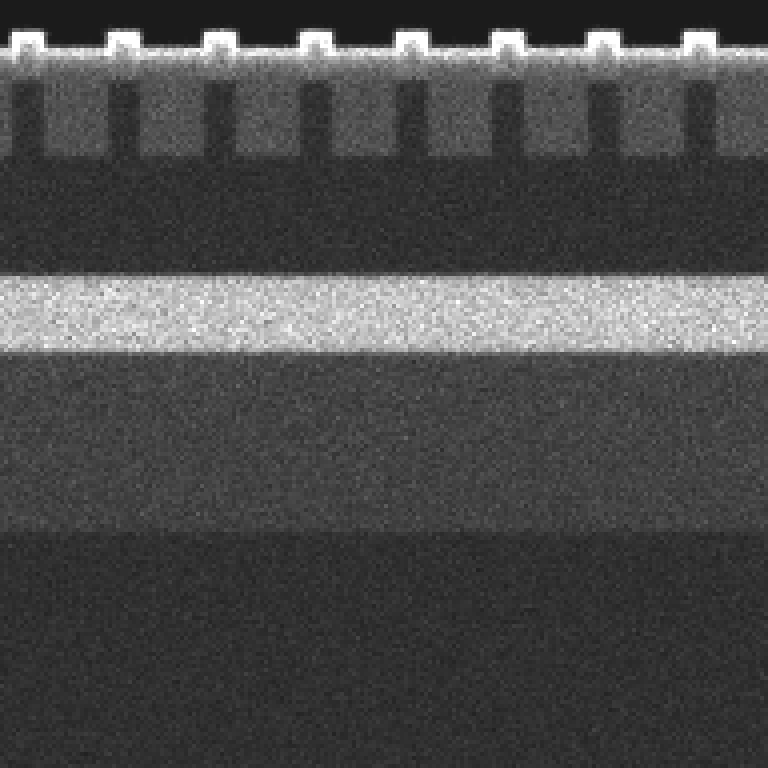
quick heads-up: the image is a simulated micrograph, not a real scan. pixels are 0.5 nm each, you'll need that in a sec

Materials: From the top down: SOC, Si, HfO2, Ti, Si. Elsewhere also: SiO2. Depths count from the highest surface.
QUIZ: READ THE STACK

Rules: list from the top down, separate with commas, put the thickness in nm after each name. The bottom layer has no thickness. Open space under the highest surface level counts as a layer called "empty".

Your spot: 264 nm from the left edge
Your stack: empty 8, SOC 54, Si 60, HfO2 38, Ti 90, Si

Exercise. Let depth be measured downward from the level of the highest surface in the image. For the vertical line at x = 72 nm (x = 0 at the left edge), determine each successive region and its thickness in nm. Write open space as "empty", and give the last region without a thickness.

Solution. empty 8, SOC 54, Si 60, HfO2 38, Ti 90, Si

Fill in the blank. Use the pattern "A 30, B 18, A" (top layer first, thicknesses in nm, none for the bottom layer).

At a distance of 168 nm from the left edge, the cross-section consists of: empty 8, SOC 54, Si 60, HfO2 38, Ti 90, Si